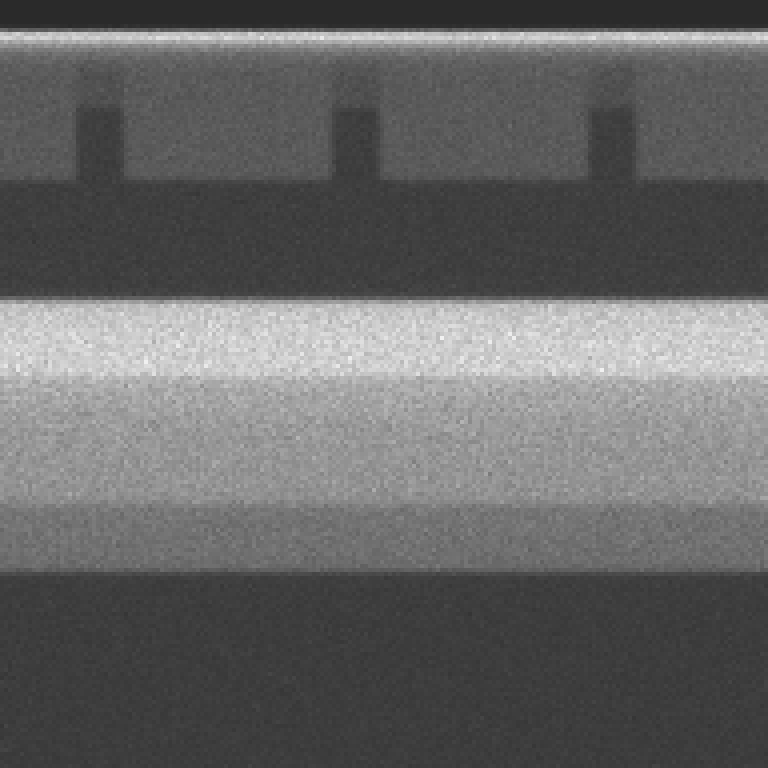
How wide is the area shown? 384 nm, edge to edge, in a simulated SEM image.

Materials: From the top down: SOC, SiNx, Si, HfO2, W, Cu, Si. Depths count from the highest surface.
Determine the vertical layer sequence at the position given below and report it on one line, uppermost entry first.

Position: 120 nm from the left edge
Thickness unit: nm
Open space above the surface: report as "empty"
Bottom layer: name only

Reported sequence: SOC 74, Si 60, HfO2 38, W 64, Cu 34, Si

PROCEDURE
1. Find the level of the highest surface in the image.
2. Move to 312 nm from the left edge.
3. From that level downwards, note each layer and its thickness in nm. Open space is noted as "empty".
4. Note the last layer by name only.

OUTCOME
SOC 12, SiNx 26, Si 96, HfO2 38, W 64, Cu 34, Si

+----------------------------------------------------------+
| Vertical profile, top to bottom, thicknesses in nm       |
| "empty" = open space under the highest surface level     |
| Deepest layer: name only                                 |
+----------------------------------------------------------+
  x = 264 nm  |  SOC 74, Si 60, HfO2 38, W 64, Cu 34, Si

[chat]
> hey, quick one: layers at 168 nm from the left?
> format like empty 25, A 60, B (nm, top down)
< SOC 12, SiNx 26, Si 96, HfO2 38, W 64, Cu 34, Si